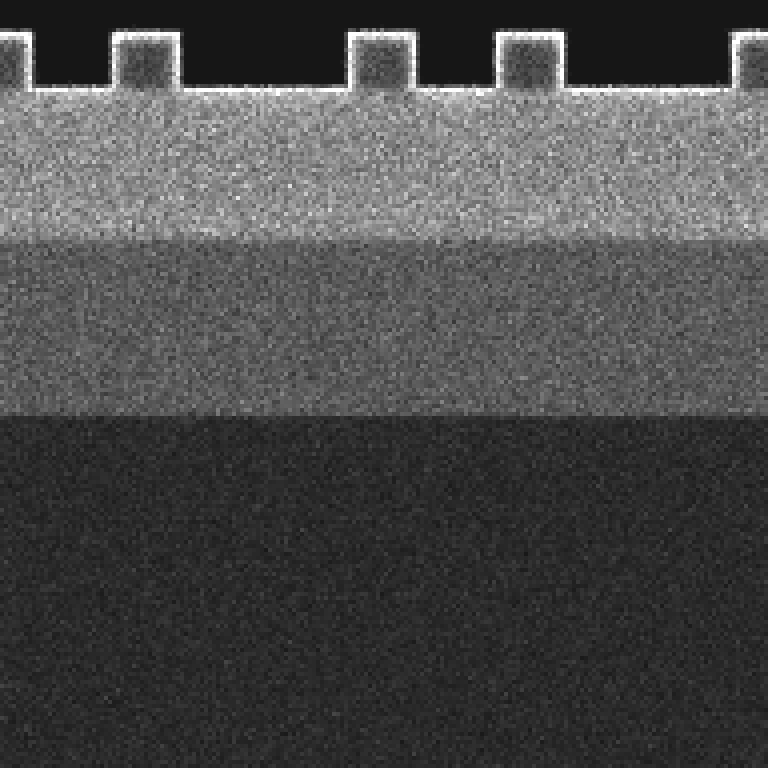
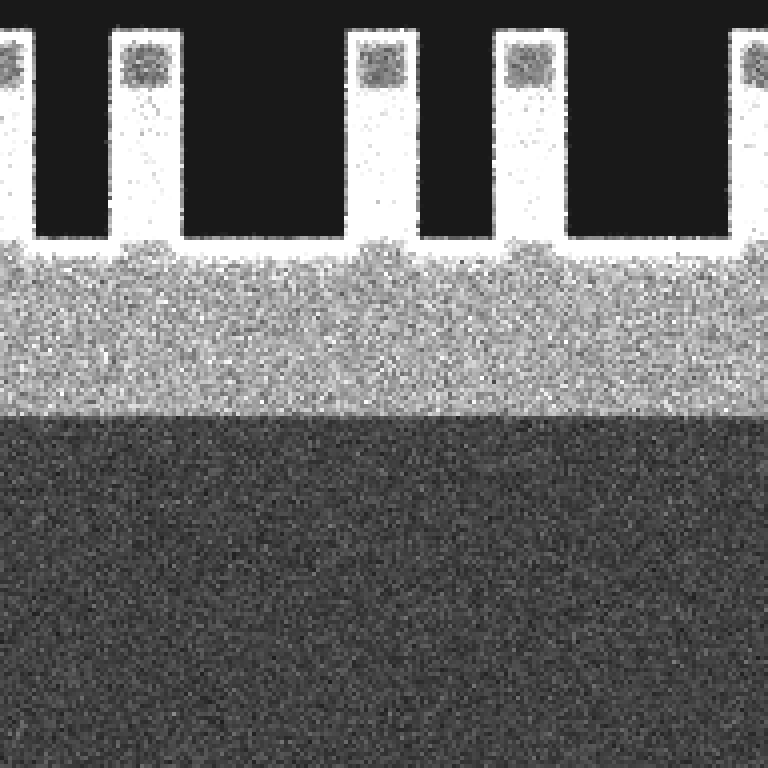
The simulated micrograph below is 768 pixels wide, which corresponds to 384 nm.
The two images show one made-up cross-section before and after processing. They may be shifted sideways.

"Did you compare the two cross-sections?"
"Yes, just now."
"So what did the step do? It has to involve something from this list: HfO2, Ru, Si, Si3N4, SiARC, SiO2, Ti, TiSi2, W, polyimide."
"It removed W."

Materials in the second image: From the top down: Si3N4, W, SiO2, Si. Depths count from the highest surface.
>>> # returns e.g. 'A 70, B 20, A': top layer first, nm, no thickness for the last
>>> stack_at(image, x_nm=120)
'empty 104, SiO2 88, Si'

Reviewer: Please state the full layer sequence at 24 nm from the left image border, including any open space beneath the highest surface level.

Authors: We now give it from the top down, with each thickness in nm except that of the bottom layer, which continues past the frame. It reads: empty 104, SiO2 88, Si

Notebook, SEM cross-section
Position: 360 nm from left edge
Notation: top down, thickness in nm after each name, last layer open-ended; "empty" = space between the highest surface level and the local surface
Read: empty 104, SiO2 88, Si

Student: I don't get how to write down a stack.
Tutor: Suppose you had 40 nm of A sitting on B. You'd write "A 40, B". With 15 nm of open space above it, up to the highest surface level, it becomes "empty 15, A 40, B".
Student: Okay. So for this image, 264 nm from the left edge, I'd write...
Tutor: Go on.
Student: Si3N4 28, W 76, SiO2 88, Si